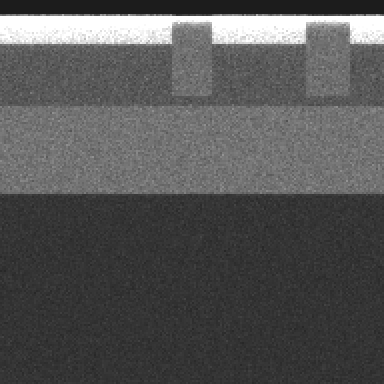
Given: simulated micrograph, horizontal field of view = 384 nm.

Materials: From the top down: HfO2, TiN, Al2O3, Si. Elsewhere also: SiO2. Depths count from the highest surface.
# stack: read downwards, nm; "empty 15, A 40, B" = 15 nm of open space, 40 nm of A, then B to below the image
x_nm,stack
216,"HfO2 28, TiN 62, Al2O3 88, Si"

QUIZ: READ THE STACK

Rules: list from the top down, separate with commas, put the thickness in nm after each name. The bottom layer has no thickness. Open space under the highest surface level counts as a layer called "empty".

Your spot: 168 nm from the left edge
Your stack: HfO2 28, TiN 62, Al2O3 88, Si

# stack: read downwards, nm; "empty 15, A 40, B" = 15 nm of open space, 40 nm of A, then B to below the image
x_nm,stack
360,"HfO2 28, TiN 62, Al2O3 88, Si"